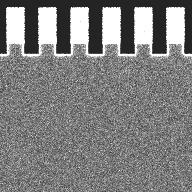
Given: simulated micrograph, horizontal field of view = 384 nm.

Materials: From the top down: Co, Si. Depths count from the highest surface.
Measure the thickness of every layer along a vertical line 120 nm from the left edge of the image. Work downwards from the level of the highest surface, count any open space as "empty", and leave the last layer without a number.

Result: empty 92, Si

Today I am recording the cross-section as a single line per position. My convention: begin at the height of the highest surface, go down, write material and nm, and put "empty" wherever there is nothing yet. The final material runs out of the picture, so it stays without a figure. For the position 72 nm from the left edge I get empty 92, Si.